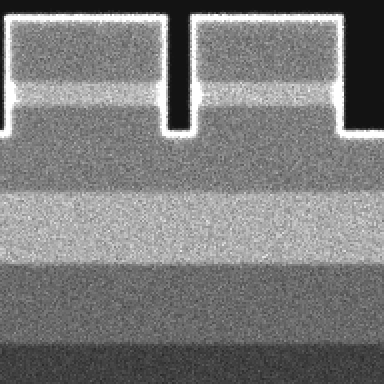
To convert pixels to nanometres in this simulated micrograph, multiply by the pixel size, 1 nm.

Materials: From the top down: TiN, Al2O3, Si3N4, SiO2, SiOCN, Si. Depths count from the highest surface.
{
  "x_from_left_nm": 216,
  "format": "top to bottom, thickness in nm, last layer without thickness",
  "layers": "TiN 66, Al2O3 24, Si3N4 86, SiO2 72, SiOCN 80, Si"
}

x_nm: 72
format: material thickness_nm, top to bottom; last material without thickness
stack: TiN 66, Al2O3 24, Si3N4 86, SiO2 72, SiOCN 80, Si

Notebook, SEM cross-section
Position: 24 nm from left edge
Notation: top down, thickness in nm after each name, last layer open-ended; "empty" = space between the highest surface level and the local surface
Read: TiN 66, Al2O3 24, Si3N4 86, SiO2 72, SiOCN 80, Si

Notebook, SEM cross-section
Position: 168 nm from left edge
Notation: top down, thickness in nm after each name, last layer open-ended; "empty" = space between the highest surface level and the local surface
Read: empty 116, Si3N4 60, SiO2 72, SiOCN 80, Si